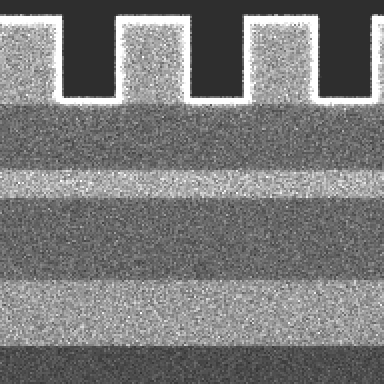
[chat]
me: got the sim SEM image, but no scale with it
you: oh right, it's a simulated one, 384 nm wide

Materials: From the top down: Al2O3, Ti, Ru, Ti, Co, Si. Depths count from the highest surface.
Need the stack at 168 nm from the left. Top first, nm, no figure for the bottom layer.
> Al2O3 88, Ti 66, Ru 28, Ti 82, Co 66, Si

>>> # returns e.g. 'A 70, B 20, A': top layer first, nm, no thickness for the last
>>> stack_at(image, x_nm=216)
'empty 82, Al2O3 6, Ti 66, Ru 28, Ti 82, Co 66, Si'